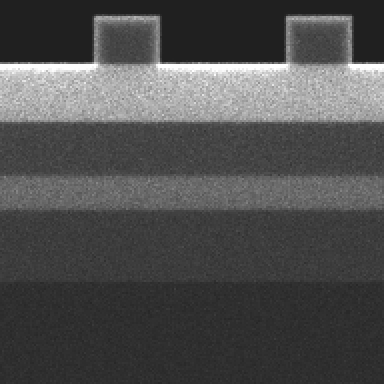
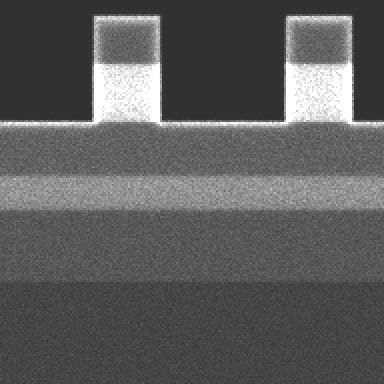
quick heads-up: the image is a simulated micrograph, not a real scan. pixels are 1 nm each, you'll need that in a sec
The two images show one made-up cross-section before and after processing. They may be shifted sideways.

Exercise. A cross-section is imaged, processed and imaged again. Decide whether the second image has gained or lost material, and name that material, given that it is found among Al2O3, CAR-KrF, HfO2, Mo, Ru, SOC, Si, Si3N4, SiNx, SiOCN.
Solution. removed: HfO2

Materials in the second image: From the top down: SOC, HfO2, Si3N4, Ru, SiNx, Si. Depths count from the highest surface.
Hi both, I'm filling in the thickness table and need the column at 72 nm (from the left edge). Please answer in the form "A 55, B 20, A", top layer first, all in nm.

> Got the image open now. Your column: empty 106, Si3N4 54, Ru 34, SiNx 72, Si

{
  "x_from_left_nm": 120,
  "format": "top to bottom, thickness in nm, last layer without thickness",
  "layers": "SOC 48, HfO2 58, Si3N4 54, Ru 34, SiNx 72, Si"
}